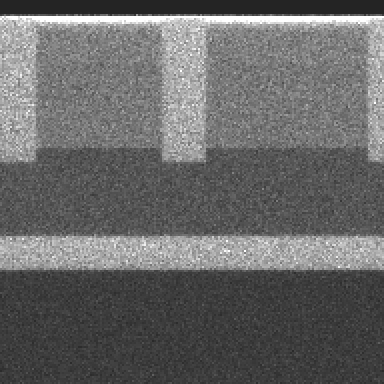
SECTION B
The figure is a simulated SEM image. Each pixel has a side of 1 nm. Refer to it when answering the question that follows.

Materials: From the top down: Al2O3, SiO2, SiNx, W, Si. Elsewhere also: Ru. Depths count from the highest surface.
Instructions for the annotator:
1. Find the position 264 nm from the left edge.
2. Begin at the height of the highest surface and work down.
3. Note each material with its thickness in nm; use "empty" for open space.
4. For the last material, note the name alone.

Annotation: Al2O3 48, SiO2 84, SiNx 88, W 34, Si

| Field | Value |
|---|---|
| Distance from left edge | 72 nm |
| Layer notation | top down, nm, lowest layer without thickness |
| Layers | Al2O3 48, SiO2 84, SiNx 88, W 34, Si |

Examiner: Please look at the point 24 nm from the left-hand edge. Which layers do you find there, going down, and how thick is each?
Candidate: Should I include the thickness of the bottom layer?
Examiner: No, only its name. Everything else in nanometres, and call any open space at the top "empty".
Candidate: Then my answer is Ru 146, SiNx 74, W 34, Si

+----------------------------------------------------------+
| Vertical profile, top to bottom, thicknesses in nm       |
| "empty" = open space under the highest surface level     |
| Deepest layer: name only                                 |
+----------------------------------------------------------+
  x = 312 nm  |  Al2O3 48, SiO2 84, SiNx 88, W 34, Si